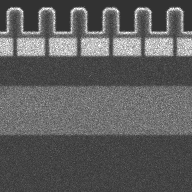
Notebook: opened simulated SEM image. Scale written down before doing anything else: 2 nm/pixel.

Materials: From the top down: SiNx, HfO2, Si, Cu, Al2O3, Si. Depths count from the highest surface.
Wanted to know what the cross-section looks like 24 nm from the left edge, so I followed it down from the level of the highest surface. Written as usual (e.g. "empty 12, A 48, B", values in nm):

SiNx 60, HfO2 36, Si 60, Cu 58, Al2O3 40, Si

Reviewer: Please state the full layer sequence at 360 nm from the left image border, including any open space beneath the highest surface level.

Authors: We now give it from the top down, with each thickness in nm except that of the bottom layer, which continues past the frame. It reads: empty 2, SiNx 58, HfO2 36, Si 60, Cu 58, Al2O3 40, Si